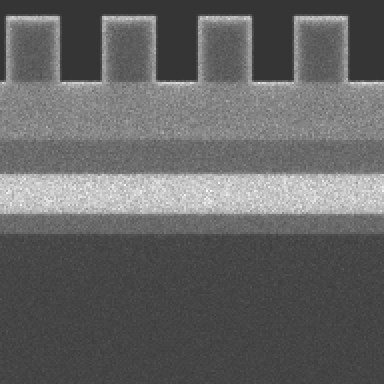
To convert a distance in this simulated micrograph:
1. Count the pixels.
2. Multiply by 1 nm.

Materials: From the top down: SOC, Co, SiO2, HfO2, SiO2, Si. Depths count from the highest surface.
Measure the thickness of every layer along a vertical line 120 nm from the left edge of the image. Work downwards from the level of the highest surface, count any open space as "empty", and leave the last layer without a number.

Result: SOC 66, Co 58, SiO2 34, HfO2 40, SiO2 20, Si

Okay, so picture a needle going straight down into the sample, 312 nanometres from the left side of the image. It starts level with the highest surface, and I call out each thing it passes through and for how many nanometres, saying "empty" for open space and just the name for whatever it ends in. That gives SOC 66, Co 58, SiO2 34, HfO2 40, SiO2 20, Si